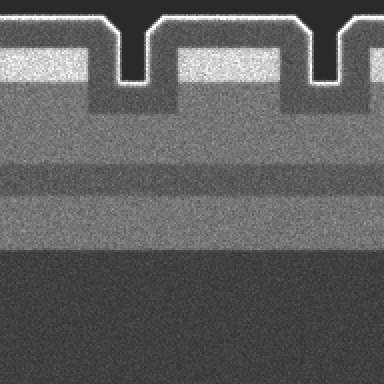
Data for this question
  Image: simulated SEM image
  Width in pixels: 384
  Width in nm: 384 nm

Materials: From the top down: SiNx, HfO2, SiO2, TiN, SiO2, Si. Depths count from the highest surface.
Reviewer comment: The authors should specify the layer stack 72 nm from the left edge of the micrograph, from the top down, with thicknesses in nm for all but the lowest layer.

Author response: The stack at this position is SiNx 32, HfO2 34, SiO2 82, TiN 32, SiO2 54, Si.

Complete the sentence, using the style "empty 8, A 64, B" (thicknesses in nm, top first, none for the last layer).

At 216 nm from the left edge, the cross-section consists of SiNx 32, HfO2 34, SiO2 82, TiN 32, SiO2 54, Si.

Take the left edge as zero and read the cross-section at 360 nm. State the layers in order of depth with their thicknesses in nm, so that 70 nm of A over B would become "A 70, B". SiNx 98, SiO2 50, TiN 32, SiO2 54, Si